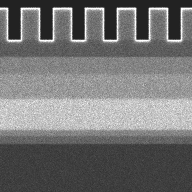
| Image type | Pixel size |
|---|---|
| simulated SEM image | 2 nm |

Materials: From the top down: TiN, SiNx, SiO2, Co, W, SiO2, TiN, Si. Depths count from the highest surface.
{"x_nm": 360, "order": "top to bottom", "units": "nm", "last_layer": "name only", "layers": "empty 64, SiNx 34, SiO2 34, Co 50, W 62, SiO2 12, TiN 16, Si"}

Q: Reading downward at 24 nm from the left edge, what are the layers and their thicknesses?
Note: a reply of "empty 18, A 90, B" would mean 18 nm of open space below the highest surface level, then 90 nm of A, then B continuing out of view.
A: empty 64, SiNx 34, SiO2 34, Co 50, W 62, SiO2 12, TiN 16, Si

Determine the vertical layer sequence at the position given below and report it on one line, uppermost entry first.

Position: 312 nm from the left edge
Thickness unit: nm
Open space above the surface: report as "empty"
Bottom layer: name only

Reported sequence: TiN 64, SiNx 34, SiO2 34, Co 50, W 62, SiO2 12, TiN 16, Si